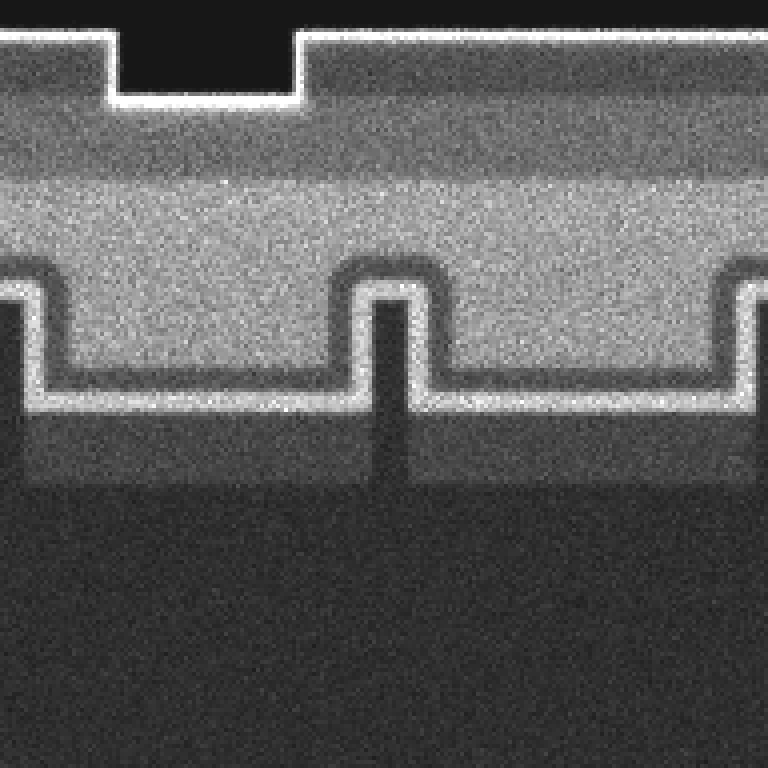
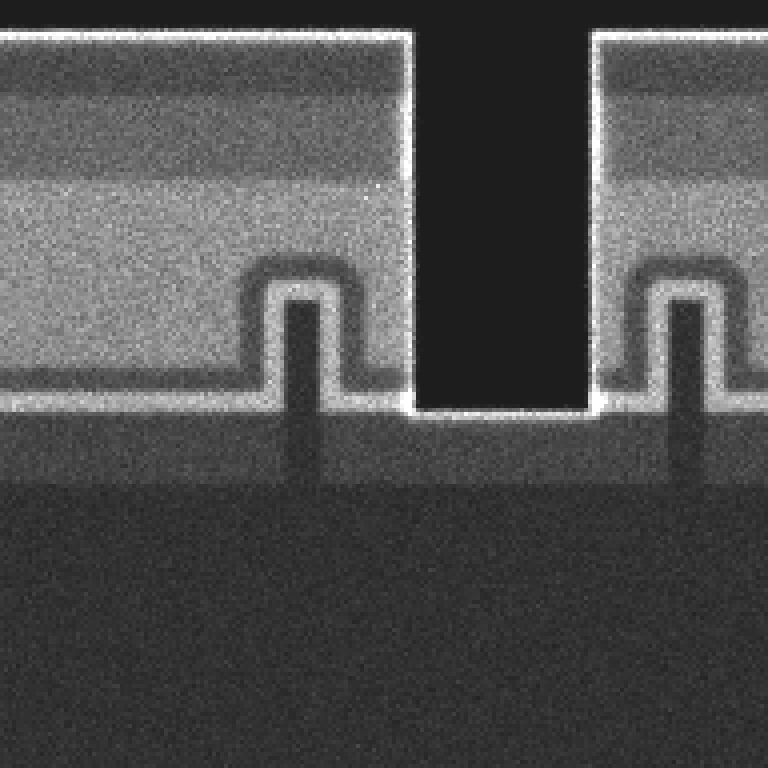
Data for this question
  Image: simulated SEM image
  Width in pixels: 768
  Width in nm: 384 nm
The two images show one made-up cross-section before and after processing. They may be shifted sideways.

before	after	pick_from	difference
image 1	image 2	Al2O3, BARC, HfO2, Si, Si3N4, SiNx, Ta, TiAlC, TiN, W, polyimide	Al2O3 and HfO2 and TiN and W removed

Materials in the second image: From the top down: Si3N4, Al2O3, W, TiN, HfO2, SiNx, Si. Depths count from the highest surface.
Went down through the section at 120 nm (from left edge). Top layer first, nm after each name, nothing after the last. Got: Si3N4 32, Al2O3 42, W 48, TiN 58, HfO2 10, SiNx 36, Si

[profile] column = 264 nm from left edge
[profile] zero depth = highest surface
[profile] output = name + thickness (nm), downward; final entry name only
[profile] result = empty 190, SiNx 36, Si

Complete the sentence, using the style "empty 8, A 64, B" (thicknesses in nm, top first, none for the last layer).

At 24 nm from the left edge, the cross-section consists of Si3N4 32, Al2O3 42, W 94, TiN 12, HfO2 10, SiNx 36, Si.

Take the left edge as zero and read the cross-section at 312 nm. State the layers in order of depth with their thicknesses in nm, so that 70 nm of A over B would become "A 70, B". Si3N4 32, Al2O3 42, W 48, TiN 58, HfO2 10, SiNx 36, Si